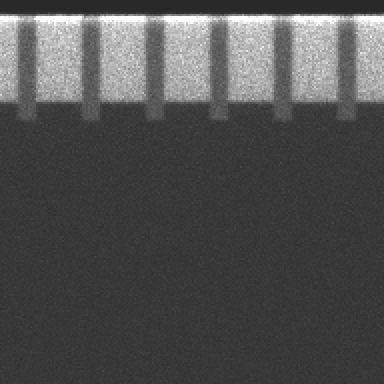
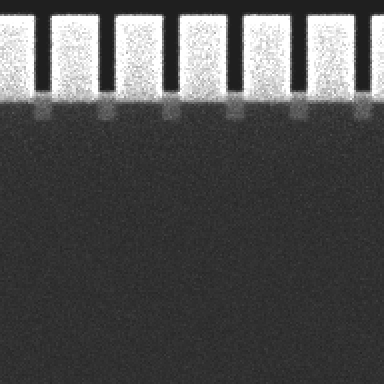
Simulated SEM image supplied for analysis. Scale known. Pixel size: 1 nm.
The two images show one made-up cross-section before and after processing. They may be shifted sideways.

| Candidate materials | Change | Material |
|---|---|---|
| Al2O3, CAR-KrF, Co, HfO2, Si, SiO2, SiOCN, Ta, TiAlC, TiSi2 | removed | SiO2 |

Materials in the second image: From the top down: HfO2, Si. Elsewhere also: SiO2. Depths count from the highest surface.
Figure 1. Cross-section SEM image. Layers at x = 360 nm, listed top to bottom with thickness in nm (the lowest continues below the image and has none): empty 76, SiO2 28, Si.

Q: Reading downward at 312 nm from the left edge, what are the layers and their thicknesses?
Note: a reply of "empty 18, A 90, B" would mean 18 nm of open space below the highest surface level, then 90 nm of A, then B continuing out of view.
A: HfO2 86, Si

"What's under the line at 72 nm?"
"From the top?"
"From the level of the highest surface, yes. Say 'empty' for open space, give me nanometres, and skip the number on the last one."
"HfO2 86, Si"